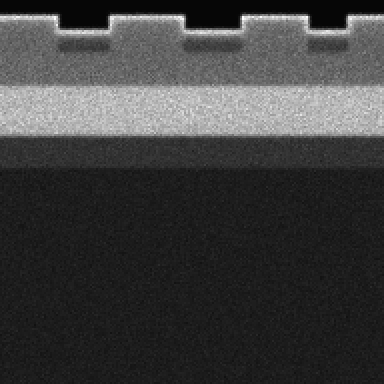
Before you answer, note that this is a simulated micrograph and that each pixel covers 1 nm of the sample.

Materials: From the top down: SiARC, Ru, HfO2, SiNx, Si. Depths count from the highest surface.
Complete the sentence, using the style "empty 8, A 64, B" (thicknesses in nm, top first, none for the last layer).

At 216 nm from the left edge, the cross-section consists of empty 14, SiARC 22, Ru 34, HfO2 50, SiNx 32, Si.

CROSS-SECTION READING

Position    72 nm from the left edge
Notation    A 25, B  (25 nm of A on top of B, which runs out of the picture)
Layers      empty 14, SiARC 22, Ru 34, HfO2 50, SiNx 32, Si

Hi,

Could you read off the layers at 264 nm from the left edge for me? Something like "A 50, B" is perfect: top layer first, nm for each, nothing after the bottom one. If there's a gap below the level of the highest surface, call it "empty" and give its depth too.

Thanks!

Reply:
Ru 70, HfO2 50, SiNx 32, Si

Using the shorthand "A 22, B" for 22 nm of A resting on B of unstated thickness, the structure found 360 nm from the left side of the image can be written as Ru 70, HfO2 50, SiNx 32, Si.